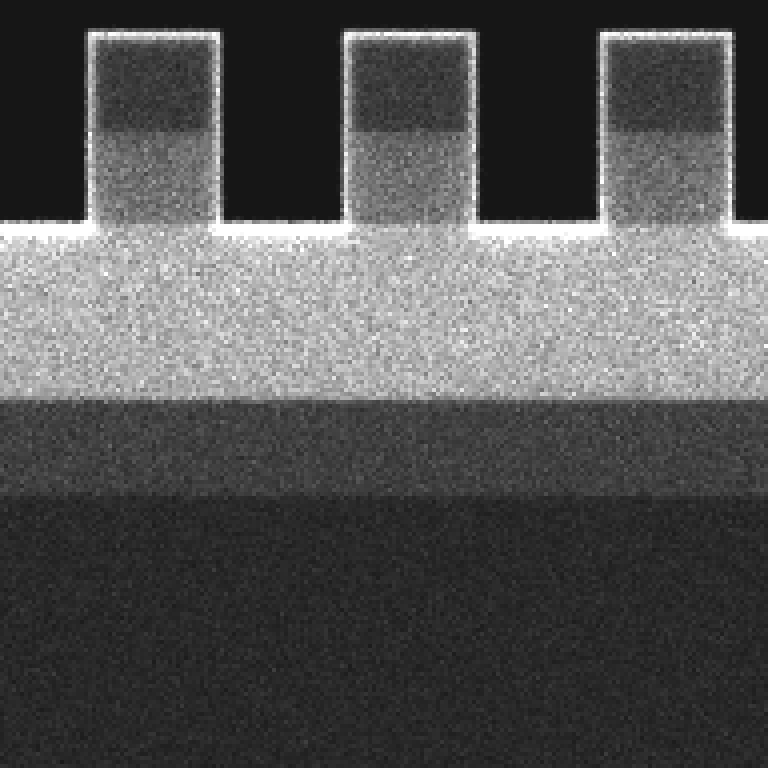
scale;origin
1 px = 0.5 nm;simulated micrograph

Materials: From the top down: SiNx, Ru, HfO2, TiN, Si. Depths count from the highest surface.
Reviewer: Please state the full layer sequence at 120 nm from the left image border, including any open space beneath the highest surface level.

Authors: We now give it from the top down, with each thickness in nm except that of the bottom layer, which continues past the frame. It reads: empty 96, HfO2 88, TiN 48, Si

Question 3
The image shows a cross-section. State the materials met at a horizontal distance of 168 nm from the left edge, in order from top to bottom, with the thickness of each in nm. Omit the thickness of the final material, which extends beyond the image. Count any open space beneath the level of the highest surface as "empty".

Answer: empty 96, HfO2 88, TiN 48, Si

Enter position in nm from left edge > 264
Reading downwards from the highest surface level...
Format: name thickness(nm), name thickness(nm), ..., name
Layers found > empty 96, HfO2 88, TiN 48, Si